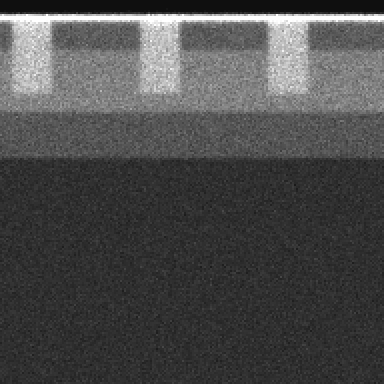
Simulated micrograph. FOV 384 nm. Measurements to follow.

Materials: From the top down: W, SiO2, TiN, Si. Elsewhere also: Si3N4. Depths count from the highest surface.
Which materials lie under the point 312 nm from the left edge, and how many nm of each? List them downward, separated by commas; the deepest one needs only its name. Si3N4 34, SiO2 62, TiN 46, Si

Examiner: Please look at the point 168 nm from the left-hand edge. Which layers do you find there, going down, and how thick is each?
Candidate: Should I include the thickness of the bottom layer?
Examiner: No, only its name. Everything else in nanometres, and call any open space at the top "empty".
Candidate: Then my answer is W 78, SiO2 18, TiN 46, Si